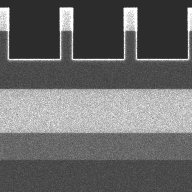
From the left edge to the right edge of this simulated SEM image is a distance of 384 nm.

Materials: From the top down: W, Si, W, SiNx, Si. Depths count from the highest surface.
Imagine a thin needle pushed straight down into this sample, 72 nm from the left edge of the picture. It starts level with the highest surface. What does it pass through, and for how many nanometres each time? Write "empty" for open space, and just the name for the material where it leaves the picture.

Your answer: empty 102, Si 60, W 88, SiNx 54, Si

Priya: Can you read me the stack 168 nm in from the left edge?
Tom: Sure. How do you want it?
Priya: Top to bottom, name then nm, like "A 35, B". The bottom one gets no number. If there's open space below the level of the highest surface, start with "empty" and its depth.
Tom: empty 102, Si 60, W 88, SiNx 54, Si